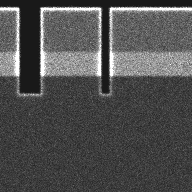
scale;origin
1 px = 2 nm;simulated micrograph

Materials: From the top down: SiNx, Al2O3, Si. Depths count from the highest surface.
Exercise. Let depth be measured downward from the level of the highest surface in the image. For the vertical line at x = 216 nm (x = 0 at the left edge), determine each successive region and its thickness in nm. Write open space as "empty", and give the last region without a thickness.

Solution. empty 172, Si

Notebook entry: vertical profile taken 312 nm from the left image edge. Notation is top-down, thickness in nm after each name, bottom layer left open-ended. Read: SiNx 88, Al2O3 48, Si